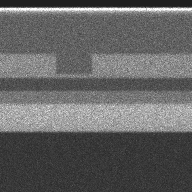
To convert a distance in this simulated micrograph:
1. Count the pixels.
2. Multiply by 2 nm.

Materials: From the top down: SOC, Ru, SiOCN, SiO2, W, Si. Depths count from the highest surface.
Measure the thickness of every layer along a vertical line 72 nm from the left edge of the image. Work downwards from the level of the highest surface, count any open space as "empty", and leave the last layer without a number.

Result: SOC 92, Ru 48, SiOCN 26, SiO2 26, W 56, Si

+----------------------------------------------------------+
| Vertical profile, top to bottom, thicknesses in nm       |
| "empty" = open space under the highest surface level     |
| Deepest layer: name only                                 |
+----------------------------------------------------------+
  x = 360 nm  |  SOC 92, Ru 48, SiOCN 26, SiO2 26, W 56, Si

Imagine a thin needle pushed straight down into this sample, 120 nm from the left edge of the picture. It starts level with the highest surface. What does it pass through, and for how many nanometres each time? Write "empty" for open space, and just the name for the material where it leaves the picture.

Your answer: SOC 132, Ru 8, SiOCN 26, SiO2 26, W 56, Si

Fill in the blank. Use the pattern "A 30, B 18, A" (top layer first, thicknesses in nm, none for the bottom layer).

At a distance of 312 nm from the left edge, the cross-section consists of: SOC 92, Ru 48, SiOCN 26, SiO2 26, W 56, Si